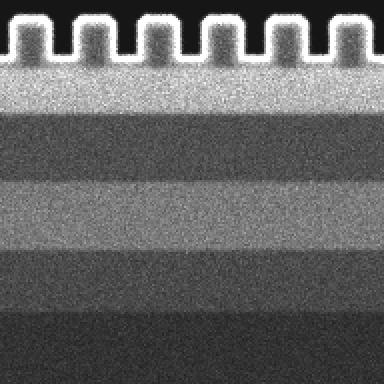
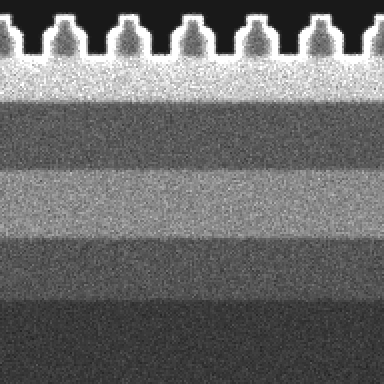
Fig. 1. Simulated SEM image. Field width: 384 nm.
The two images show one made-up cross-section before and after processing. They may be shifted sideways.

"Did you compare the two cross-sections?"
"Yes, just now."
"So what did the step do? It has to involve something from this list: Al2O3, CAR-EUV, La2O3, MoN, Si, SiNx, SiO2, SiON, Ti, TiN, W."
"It removed Al2O3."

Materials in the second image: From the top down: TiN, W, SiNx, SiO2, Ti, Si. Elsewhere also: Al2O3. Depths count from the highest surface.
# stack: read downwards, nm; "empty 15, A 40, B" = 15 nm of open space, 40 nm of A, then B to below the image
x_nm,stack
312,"TiN 40, W 46, SiNx 68, SiO2 68, Ti 62, Si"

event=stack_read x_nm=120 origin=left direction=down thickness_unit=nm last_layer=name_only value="TiN 40, W 46, SiNx 68, SiO2 68, Ti 62, Si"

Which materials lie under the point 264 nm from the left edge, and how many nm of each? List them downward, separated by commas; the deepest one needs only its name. TiN 40, W 46, SiNx 68, SiO2 68, Ti 62, Si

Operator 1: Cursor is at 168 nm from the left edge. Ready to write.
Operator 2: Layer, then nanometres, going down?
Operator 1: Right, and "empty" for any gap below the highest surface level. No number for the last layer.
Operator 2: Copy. empty 40, W 46, SiNx 68, SiO2 68, Ti 62, Si